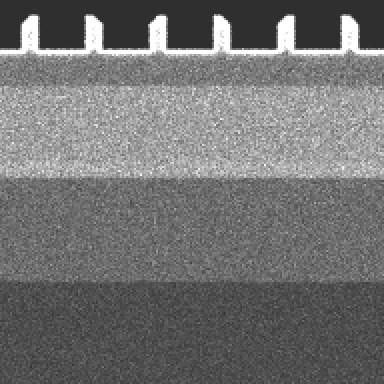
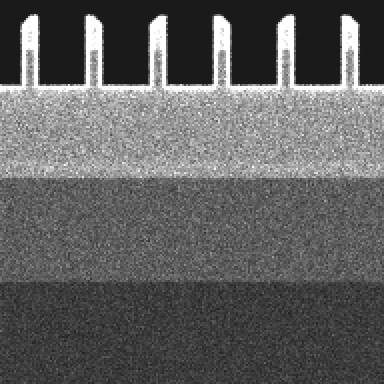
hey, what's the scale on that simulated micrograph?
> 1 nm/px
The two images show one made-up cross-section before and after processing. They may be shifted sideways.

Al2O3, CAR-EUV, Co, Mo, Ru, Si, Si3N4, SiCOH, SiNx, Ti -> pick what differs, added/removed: Si3N4 removed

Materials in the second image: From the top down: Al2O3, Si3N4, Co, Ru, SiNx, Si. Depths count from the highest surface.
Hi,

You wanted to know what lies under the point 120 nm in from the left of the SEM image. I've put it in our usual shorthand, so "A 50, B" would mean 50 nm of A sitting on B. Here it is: empty 70, Co 76, Ru 16, SiNx 104, Si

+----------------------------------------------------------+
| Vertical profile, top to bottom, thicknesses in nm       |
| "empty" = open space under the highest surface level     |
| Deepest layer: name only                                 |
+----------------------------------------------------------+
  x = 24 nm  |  empty 6, Al2O3 28, Si3N4 36, Co 76, Ru 16, SiNx 104, Si